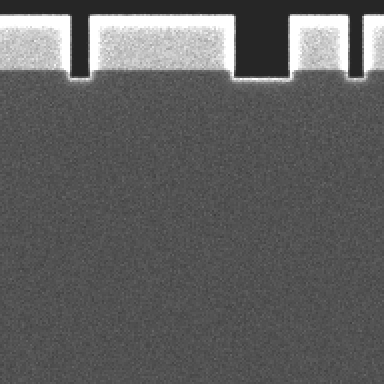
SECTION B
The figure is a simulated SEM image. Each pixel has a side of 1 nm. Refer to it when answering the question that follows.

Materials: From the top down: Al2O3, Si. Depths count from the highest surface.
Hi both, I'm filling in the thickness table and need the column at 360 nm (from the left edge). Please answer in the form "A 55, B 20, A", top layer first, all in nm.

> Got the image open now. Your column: empty 62, Si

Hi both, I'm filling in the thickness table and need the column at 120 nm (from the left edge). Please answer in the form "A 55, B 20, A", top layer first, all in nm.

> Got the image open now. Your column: Al2O3 54, Si